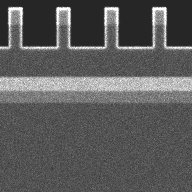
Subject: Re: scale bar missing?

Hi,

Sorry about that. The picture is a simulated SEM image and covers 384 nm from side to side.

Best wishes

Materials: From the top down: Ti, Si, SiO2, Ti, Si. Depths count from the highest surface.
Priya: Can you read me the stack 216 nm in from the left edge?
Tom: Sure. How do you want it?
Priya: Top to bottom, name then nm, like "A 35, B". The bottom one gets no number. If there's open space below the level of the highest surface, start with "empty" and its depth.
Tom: Ti 34, Si 104, SiO2 28, Ti 24, Si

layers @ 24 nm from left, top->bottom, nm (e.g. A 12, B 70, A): Ti 34, Si 104, SiO2 28, Ti 24, Si